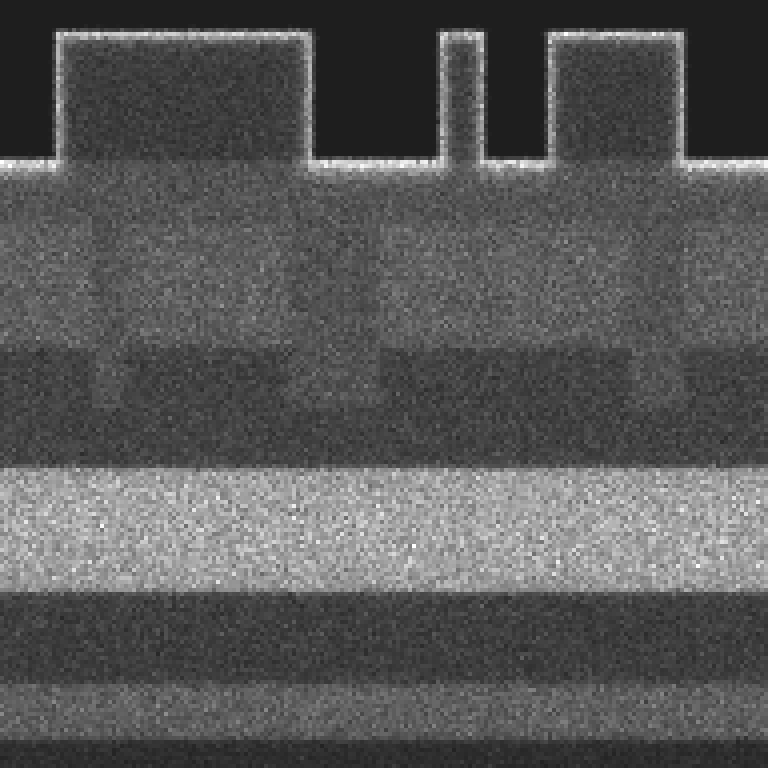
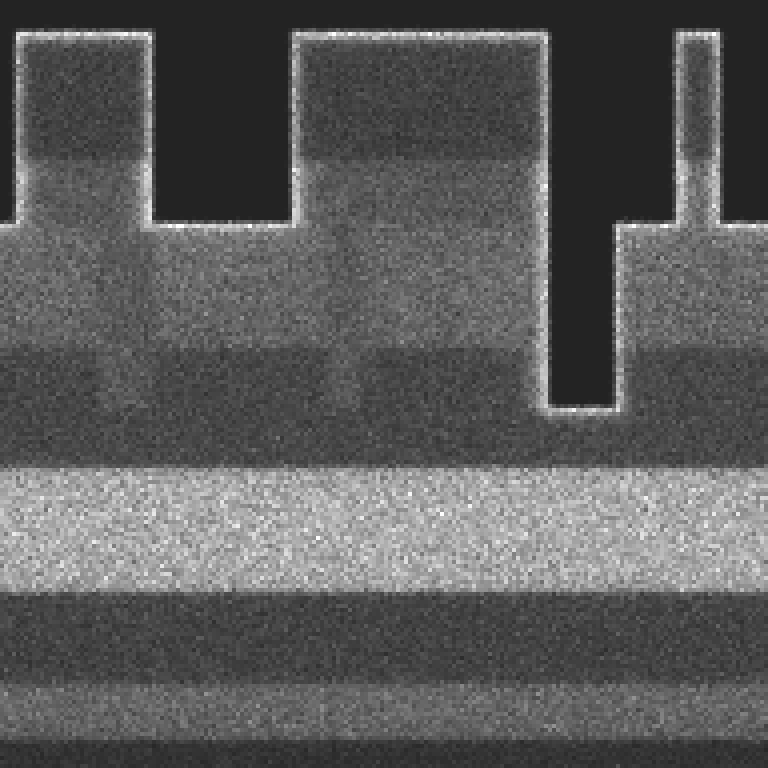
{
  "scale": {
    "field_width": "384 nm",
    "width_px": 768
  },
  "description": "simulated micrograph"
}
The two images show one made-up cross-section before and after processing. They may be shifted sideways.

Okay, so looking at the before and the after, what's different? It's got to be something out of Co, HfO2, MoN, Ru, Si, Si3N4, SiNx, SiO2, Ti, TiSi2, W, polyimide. SiO2, removed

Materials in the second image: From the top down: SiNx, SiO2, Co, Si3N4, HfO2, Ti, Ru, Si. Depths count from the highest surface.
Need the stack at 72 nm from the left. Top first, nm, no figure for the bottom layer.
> SiNx 64, SiO2 124, Si3N4 30, HfO2 62, Ti 46, Ru 28, Si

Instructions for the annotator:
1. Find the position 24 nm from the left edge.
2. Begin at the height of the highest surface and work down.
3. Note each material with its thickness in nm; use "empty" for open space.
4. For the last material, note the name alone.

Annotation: SiNx 64, SiO2 32, Co 62, Si3N4 60, HfO2 62, Ti 46, Ru 28, Si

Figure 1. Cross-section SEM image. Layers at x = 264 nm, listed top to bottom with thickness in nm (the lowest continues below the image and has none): SiNx 64, SiO2 124, Si3N4 30, HfO2 62, Ti 46, Ru 28, Si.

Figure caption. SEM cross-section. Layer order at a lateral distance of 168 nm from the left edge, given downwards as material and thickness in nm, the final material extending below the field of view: SiNx 64, SiO2 124, Si3N4 30, HfO2 62, Ti 46, Ru 28, Si